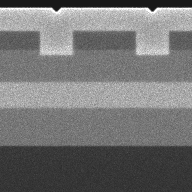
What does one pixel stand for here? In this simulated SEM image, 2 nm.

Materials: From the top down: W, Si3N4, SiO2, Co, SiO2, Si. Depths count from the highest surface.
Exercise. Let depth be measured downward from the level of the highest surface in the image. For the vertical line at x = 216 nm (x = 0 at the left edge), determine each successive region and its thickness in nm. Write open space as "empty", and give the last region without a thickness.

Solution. W 46, Si3N4 38, SiO2 64, Co 52, SiO2 76, Si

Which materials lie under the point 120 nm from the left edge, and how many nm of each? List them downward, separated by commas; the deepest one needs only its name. empty 2, W 92, SiO2 54, Co 52, SiO2 76, Si